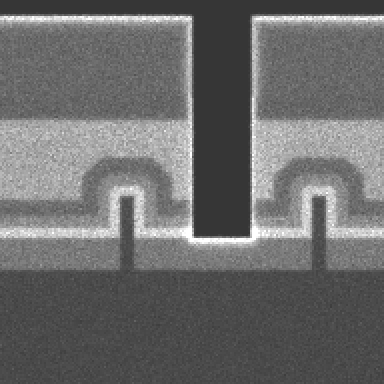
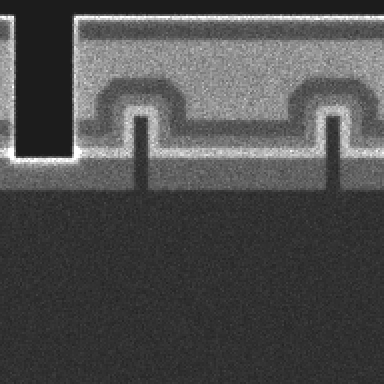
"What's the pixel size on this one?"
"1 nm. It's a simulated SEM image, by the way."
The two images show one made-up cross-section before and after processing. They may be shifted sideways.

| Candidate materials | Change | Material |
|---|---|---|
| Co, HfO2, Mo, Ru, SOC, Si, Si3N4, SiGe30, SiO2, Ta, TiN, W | removed | SOC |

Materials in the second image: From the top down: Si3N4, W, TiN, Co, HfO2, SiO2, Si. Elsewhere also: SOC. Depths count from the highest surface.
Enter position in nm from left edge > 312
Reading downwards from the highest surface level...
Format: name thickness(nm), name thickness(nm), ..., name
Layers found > Si3N4 24, W 38, TiN 18, Co 52, HfO2 10, SiO2 32, Si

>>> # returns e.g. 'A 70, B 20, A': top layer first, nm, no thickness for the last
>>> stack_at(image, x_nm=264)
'Si3N4 24, W 80, TiN 16, Co 12, HfO2 10, SiO2 32, Si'